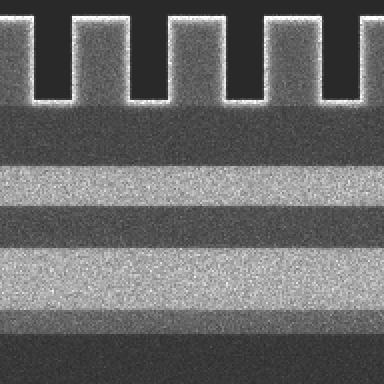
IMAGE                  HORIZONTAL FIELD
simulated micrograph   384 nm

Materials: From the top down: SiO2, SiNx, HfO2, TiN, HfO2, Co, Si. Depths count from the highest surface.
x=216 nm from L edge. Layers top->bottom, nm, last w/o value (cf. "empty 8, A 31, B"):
SiO2 90, SiNx 60, HfO2 40, TiN 42, HfO2 62, Co 24, Si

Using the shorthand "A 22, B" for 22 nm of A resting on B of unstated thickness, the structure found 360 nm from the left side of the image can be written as SiO2 90, SiNx 60, HfO2 40, TiN 42, HfO2 62, Co 24, Si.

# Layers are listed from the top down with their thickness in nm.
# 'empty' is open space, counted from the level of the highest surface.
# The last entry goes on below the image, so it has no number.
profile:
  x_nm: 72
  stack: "SiO2 90, SiNx 60, HfO2 40, TiN 42, HfO2 62, Co 24, Si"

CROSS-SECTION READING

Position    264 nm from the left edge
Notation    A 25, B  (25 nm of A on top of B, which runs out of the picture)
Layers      SiO2 90, SiNx 60, HfO2 40, TiN 42, HfO2 62, Co 24, Si